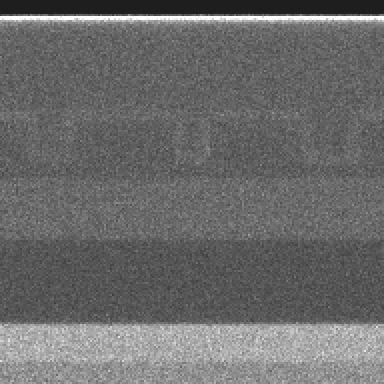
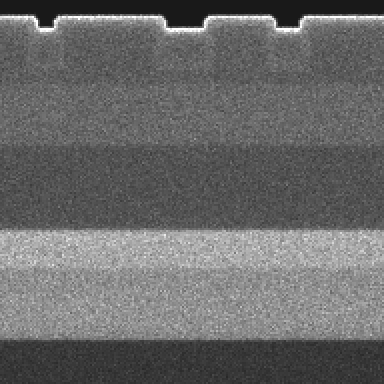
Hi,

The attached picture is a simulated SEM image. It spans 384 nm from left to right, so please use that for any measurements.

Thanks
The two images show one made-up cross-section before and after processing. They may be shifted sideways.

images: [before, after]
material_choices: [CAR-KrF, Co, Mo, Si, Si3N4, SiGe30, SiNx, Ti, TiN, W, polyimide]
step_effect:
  removed: Si3N4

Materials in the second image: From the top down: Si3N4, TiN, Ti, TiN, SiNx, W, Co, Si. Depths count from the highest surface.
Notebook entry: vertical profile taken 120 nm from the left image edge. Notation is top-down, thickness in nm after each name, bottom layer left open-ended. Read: TiN 10, Ti 58, TiN 62, SiNx 84, W 38, Co 72, Si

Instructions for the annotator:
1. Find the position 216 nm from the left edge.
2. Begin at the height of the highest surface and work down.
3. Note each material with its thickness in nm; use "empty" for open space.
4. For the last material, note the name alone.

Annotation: TiN 10, Ti 58, TiN 62, SiNx 84, W 38, Co 72, Si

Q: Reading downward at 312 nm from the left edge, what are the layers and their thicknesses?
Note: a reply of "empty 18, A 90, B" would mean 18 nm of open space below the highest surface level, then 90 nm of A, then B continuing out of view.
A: TiN 10, Ti 58, TiN 62, SiNx 84, W 38, Co 72, Si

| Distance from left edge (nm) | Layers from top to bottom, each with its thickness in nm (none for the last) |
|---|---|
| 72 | TiN 10, Ti 58, TiN 62, SiNx 84, W 38, Co 72, Si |